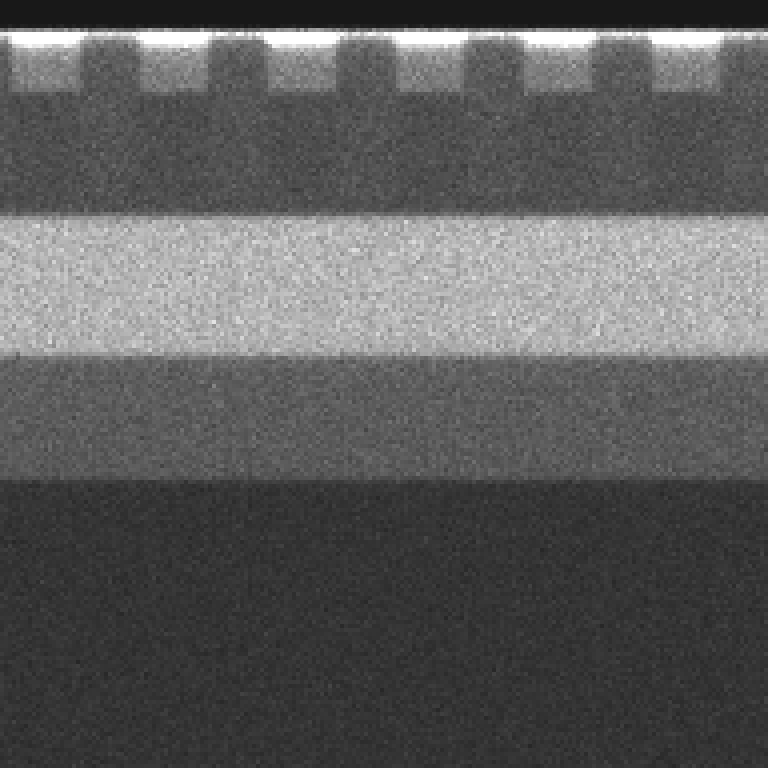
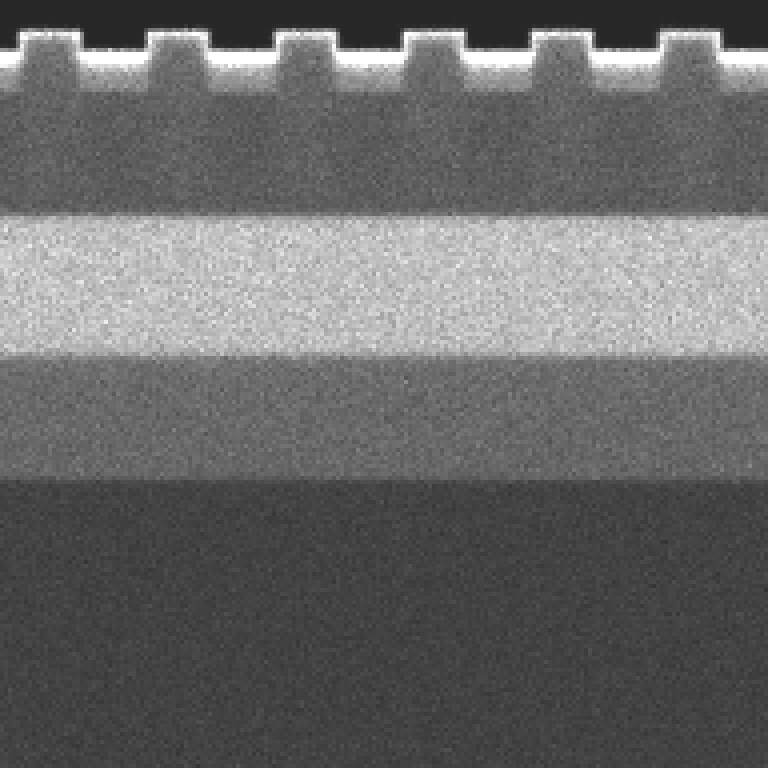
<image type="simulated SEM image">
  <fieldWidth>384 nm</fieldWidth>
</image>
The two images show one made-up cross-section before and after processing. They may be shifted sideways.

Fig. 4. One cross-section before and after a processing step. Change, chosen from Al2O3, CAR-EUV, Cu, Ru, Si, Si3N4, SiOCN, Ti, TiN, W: Al2O3 removed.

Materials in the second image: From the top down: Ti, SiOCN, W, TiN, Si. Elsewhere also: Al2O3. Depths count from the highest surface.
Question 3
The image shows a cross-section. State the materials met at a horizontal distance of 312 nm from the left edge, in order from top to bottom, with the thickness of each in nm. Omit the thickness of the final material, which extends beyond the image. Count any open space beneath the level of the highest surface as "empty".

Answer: empty 10, Al2O3 20, SiOCN 62, W 70, TiN 62, Si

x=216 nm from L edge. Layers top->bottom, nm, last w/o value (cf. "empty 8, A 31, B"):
Ti 82, SiOCN 10, W 70, TiN 62, Si